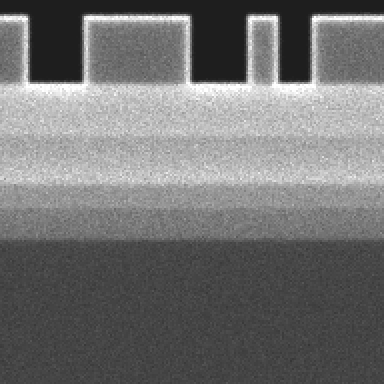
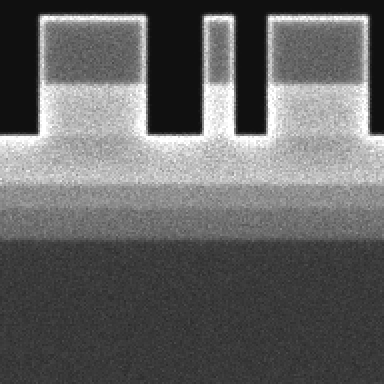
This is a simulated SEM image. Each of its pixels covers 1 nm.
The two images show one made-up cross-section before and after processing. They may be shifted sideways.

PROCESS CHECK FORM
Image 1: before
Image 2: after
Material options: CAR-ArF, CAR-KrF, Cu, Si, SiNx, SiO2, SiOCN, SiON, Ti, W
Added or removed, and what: removed, W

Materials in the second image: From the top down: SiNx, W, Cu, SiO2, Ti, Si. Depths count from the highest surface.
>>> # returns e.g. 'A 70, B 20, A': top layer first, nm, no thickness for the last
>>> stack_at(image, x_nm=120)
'SiNx 68, W 52, Cu 48, SiO2 24, Ti 32, Si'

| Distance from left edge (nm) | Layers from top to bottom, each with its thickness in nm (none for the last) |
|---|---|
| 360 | SiNx 68, W 52, Cu 48, SiO2 24, Ti 32, Si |